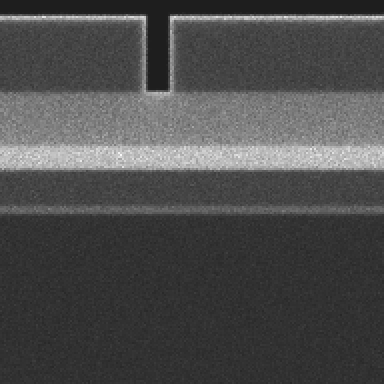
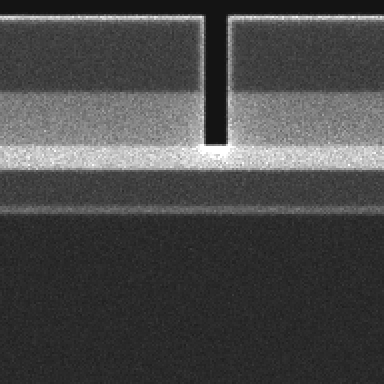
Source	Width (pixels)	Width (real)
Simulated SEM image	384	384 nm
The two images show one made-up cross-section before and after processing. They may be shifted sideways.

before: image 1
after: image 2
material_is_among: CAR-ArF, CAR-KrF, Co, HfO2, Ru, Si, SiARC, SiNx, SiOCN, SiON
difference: Ru, removed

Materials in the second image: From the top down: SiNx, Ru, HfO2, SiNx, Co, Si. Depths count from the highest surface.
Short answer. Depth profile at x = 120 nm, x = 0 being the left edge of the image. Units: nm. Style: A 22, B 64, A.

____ SiNx 76, Ru 54, HfO2 24, SiNx 36, Co 8, Si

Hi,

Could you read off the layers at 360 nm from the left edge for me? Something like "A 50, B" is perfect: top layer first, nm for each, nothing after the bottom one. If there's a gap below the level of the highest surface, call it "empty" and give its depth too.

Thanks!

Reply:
SiNx 76, Ru 54, HfO2 24, SiNx 36, Co 8, Si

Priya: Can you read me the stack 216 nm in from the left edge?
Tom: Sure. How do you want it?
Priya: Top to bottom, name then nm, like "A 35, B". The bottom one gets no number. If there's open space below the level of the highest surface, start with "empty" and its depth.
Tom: empty 130, HfO2 24, SiNx 36, Co 8, Si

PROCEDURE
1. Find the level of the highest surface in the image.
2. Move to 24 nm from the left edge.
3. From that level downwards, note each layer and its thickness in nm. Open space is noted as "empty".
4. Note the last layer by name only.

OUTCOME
SiNx 76, Ru 54, HfO2 24, SiNx 36, Co 8, Si